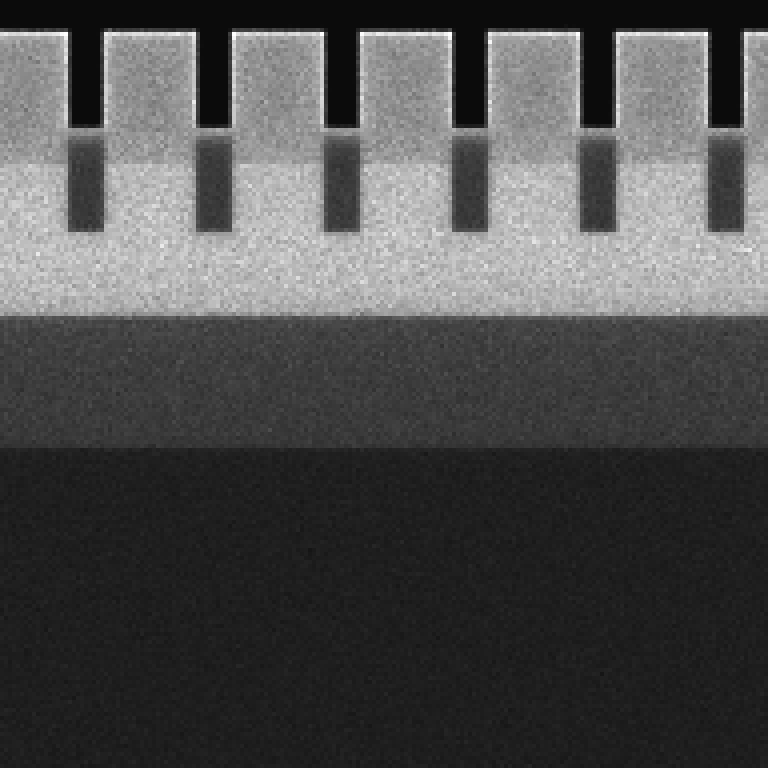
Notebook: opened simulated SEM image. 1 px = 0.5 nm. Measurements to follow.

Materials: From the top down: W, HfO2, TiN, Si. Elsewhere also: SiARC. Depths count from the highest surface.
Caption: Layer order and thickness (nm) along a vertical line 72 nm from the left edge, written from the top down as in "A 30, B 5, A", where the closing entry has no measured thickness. W 66, HfO2 76, TiN 66, Si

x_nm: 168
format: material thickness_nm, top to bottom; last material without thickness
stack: empty 48, SiARC 52, HfO2 42, TiN 66, Si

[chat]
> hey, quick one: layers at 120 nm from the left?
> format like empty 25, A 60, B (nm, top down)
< W 66, HfO2 76, TiN 66, Si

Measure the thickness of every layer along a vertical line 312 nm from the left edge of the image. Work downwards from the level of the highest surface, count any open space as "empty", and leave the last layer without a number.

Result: W 66, HfO2 76, TiN 66, Si